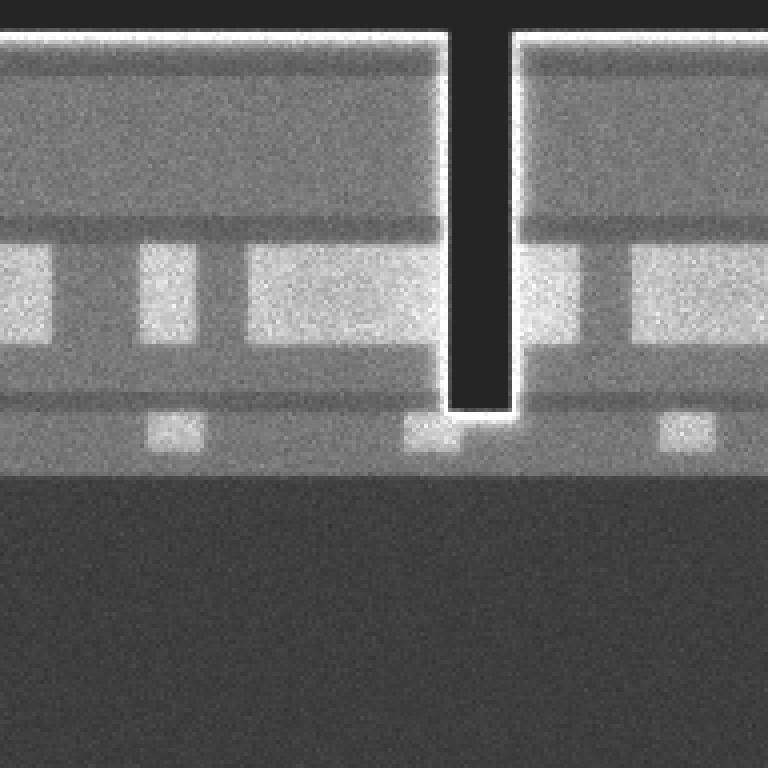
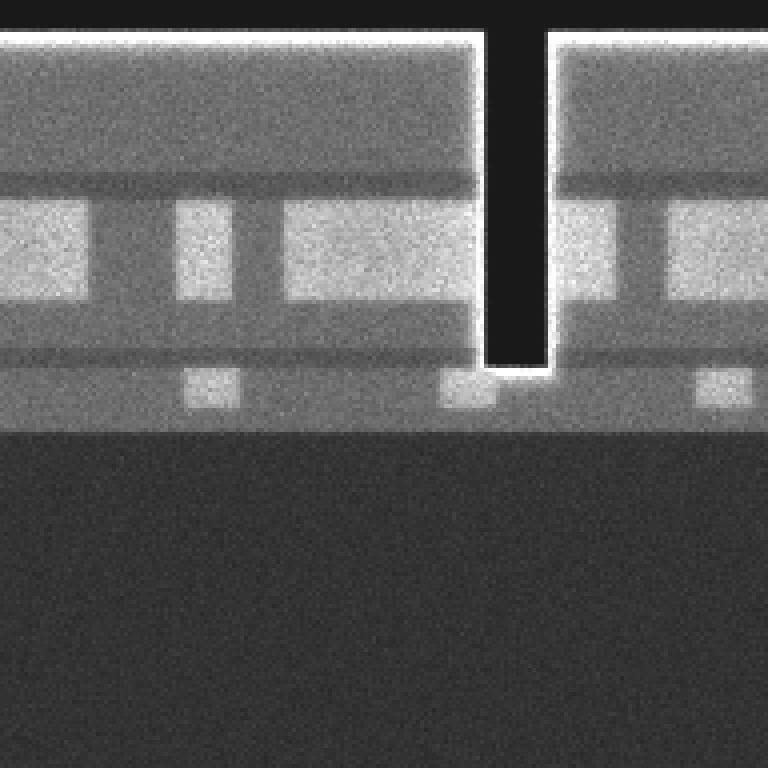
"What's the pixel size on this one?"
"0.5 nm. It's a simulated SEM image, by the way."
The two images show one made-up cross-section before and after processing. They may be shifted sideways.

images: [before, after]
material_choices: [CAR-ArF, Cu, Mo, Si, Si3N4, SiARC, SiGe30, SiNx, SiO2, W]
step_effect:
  removed: SiARC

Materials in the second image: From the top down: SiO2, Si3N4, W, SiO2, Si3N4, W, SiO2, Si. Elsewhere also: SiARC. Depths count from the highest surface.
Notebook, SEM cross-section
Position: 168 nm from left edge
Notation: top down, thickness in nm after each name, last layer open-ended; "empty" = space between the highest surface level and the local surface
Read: SiO2 70, Si3N4 14, W 50, SiO2 24, Si3N4 10, SiO2 32, Si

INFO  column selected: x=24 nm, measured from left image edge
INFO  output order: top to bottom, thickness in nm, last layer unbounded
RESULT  SiO2 70, Si3N4 14, W 50, SiO2 24, Si3N4 10, SiO2 32, Si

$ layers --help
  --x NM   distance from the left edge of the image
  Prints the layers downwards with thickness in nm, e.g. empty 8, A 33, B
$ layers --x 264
empty 168, SiO2 32, Si